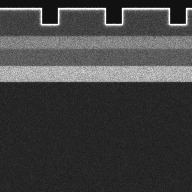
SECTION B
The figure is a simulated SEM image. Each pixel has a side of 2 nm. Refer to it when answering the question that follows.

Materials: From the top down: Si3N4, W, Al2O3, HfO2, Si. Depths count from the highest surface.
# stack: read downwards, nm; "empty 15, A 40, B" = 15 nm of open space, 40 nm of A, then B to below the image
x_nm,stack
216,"empty 32, Si3N4 24, W 26, Al2O3 34, HfO2 32, Si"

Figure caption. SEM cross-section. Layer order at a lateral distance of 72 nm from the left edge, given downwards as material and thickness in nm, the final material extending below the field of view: Si3N4 56, W 26, Al2O3 34, HfO2 32, Si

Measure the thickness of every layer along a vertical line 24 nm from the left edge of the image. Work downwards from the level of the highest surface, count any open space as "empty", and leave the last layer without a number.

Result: Si3N4 56, W 26, Al2O3 34, HfO2 32, Si